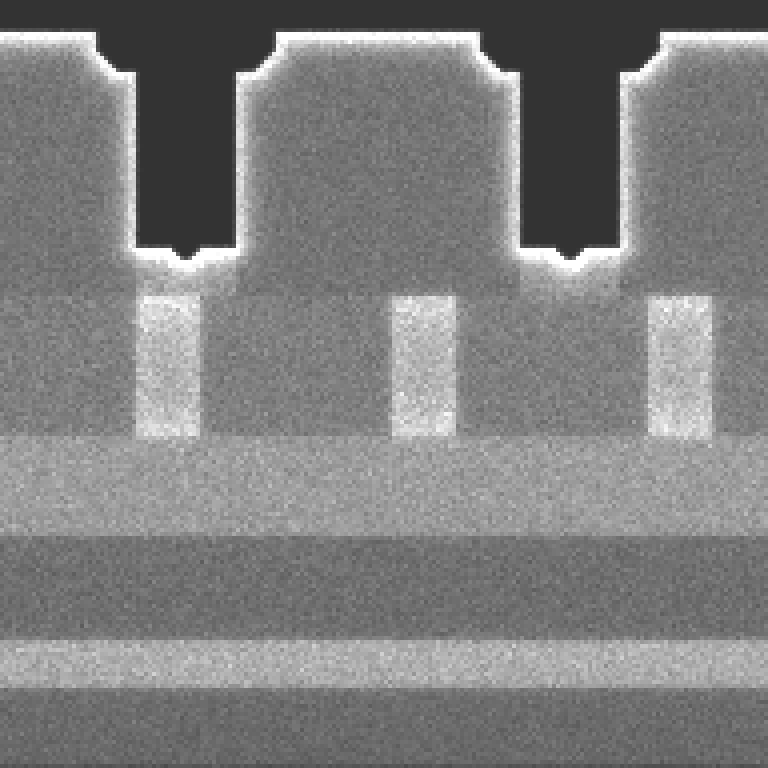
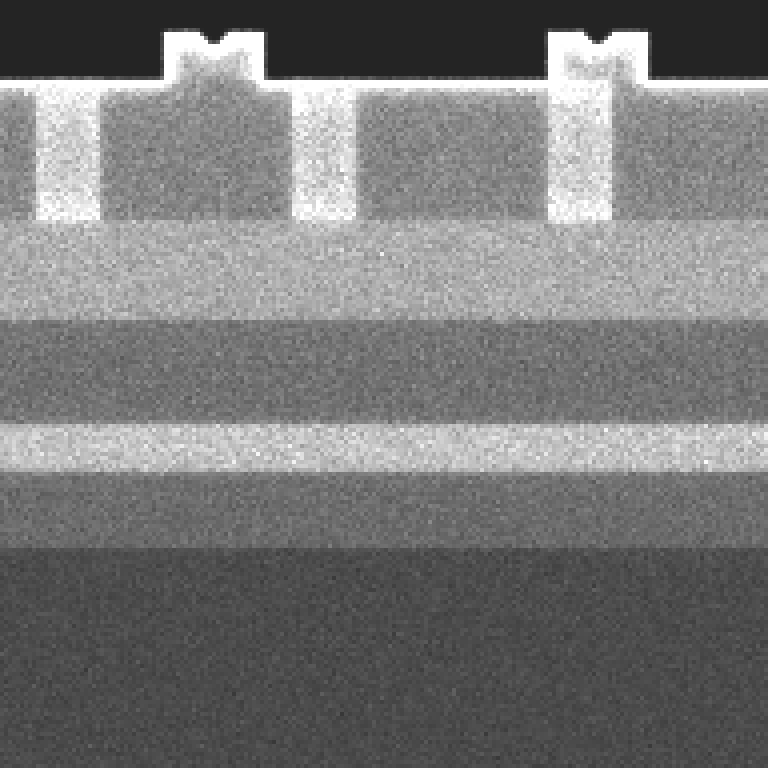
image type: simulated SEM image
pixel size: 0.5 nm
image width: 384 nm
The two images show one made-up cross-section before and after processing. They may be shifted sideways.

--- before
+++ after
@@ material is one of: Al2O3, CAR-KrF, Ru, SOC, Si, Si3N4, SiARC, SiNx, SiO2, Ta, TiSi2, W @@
SOC removed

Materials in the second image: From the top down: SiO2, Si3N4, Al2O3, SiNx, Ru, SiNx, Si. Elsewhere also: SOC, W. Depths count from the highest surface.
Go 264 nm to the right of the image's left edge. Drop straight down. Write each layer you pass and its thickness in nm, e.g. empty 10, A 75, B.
empty 24, Si3N4 70, Al2O3 50, SiNx 52, Ru 24, SiNx 38, Si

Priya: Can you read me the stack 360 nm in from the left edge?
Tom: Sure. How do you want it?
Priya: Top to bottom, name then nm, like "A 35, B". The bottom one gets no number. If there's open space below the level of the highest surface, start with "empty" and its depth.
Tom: empty 24, Si3N4 70, Al2O3 50, SiNx 52, Ru 24, SiNx 38, Si